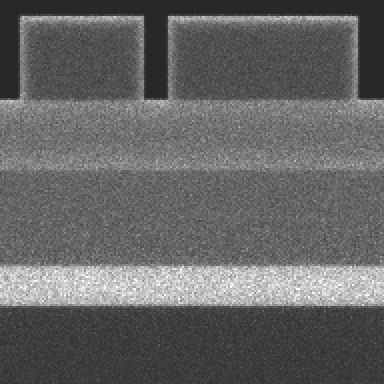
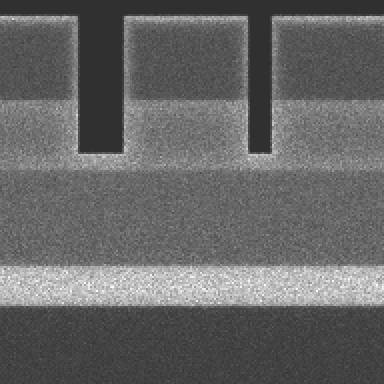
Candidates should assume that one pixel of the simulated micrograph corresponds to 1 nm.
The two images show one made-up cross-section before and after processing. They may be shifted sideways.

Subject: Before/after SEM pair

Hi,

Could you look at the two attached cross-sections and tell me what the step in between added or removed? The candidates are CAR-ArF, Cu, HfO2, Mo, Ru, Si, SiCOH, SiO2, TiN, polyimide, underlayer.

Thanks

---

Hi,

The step removed Ru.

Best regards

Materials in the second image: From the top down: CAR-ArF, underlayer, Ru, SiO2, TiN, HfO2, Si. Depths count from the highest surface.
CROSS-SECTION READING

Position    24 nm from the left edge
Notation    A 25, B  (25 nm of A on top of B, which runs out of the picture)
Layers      CAR-ArF 54, underlayer 30, Ru 70, SiO2 50, TiN 46, HfO2 40, Si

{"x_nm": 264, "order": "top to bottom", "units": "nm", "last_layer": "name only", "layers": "empty 138, Ru 16, SiO2 50, TiN 46, HfO2 40, Si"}